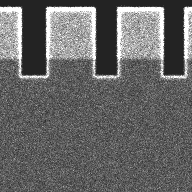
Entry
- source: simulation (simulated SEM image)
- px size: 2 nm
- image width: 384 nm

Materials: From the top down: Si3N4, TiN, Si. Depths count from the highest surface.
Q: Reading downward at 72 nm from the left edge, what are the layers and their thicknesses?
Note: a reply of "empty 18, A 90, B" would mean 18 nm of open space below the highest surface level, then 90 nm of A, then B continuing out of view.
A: empty 136, Si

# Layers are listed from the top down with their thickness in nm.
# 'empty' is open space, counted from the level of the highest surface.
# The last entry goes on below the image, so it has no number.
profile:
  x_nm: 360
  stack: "empty 136, Si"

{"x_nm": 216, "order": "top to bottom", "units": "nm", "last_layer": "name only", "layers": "empty 136, Si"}